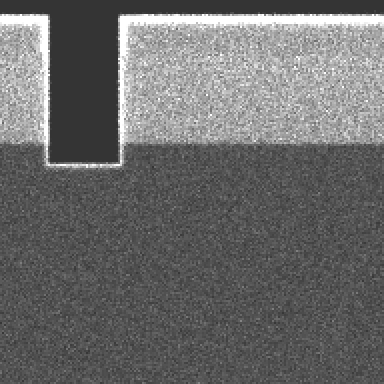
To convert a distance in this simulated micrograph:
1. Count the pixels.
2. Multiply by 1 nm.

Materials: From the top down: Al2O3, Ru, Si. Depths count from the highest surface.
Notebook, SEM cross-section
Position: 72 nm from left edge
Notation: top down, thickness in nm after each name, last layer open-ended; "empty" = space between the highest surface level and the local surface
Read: empty 148, Si